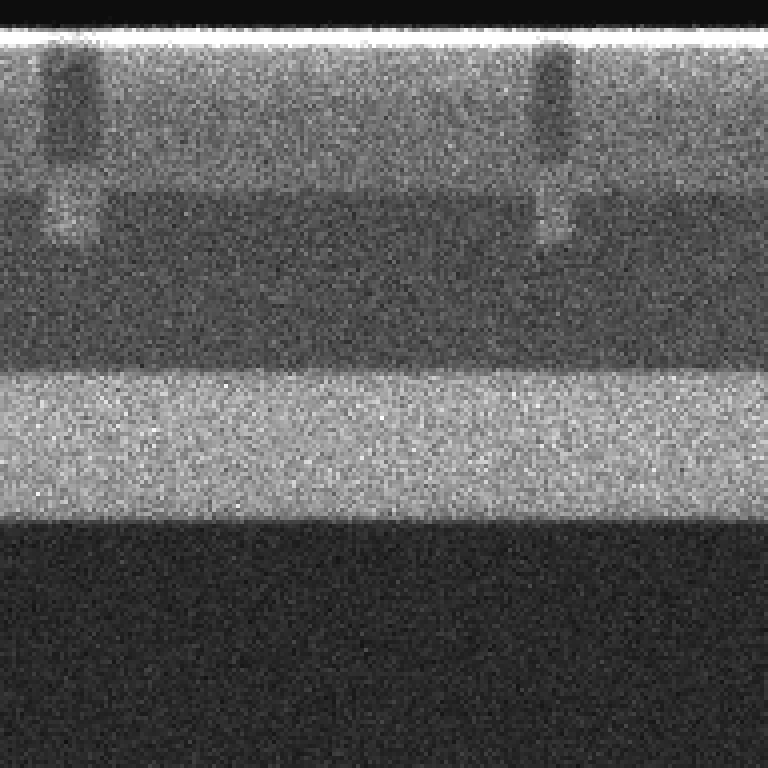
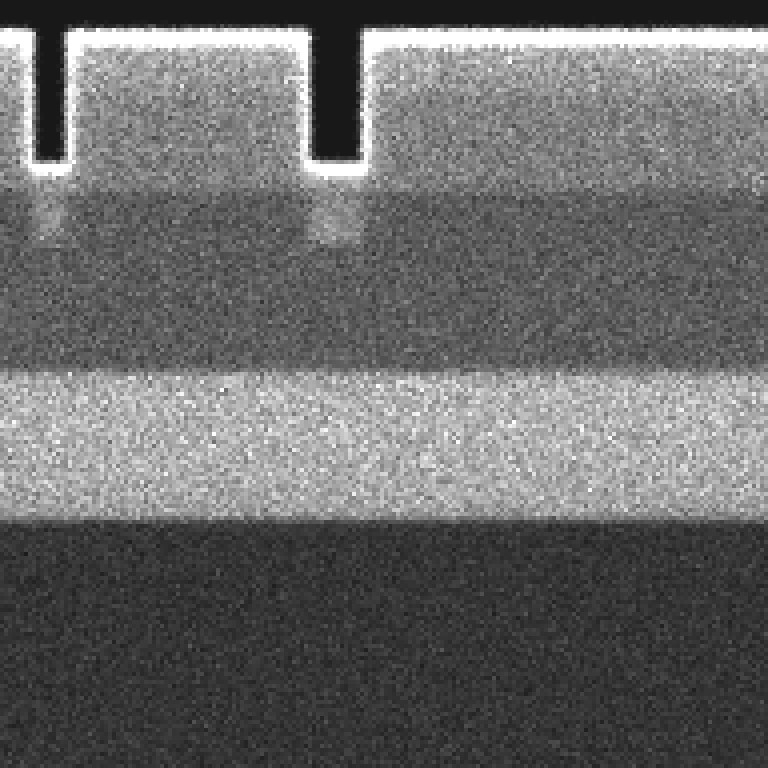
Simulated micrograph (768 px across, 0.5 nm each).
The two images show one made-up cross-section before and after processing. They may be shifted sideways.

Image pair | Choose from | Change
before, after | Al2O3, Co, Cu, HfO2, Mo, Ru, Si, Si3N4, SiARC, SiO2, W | SiARC (removed)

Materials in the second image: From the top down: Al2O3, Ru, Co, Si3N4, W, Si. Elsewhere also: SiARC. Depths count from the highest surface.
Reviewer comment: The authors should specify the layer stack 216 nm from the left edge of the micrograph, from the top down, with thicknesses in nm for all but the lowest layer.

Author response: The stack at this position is Al2O3 12, Ru 20, Co 48, Si3N4 90, W 74, Si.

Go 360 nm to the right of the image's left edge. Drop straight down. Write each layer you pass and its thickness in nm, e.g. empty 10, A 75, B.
Al2O3 12, Ru 20, Co 48, Si3N4 90, W 74, Si